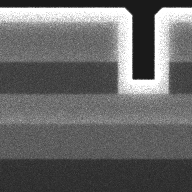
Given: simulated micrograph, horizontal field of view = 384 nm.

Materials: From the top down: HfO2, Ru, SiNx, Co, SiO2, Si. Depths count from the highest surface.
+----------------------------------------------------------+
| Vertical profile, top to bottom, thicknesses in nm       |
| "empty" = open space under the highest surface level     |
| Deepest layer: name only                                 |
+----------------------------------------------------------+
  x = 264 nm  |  empty 144, HfO2 28, Co 60, SiO2 70, Si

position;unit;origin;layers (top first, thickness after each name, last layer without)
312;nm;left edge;empty 12, HfO2 160, Co 60, SiO2 70, Si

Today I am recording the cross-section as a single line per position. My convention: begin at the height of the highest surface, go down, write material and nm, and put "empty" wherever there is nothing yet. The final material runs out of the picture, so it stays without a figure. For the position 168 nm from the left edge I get HfO2 28, Ru 80, SiNx 64, Co 60, SiO2 70, Si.